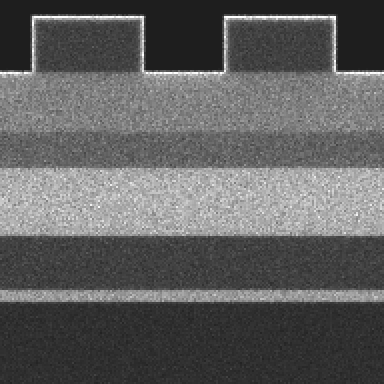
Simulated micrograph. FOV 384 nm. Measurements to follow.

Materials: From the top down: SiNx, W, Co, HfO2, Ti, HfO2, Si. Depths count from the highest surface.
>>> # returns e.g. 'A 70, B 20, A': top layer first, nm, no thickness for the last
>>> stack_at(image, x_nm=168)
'empty 56, W 60, Co 36, HfO2 68, Ti 54, HfO2 12, Si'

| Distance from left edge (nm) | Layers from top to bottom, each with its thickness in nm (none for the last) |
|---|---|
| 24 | empty 56, W 60, Co 36, HfO2 68, Ti 54, HfO2 12, Si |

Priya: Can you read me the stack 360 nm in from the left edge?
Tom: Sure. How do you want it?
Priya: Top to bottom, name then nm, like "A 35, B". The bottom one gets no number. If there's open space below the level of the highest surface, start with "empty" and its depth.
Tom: empty 56, W 60, Co 36, HfO2 68, Ti 54, HfO2 12, Si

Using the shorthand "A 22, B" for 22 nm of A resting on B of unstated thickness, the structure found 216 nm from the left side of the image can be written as empty 56, W 60, Co 36, HfO2 68, Ti 54, HfO2 12, Si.